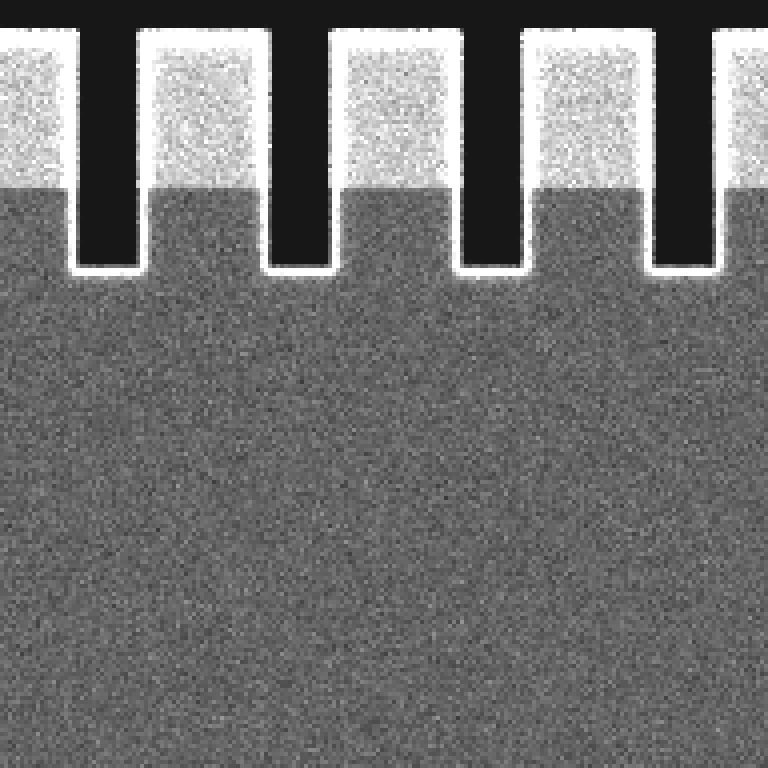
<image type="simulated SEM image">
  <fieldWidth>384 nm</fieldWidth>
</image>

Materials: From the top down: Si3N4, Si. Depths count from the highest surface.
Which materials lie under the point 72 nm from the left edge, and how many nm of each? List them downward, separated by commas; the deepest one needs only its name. Si3N4 78, Si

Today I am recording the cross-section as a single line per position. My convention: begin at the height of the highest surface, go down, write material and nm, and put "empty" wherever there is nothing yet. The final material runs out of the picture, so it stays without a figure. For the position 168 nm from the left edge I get Si3N4 78, Si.